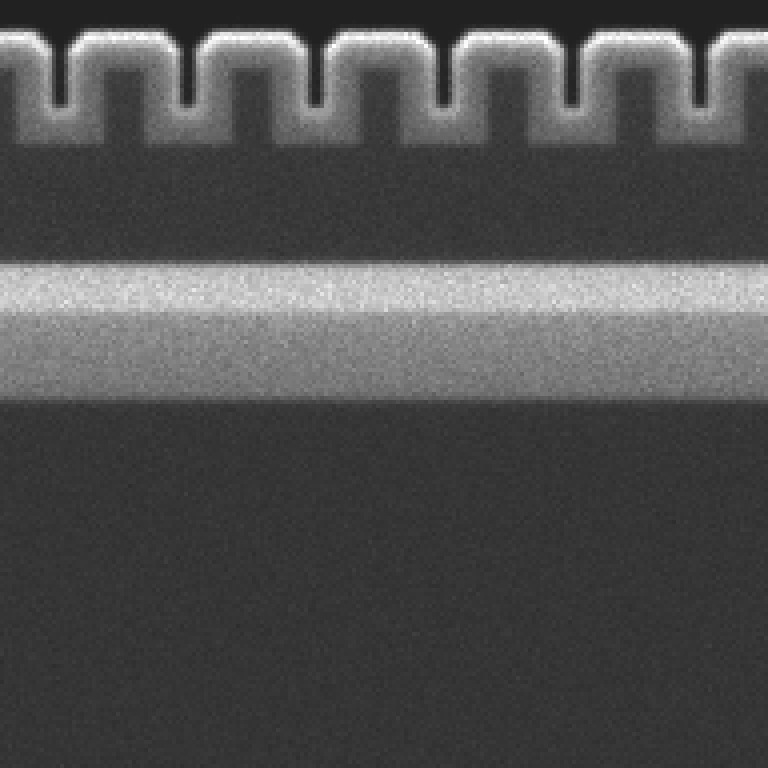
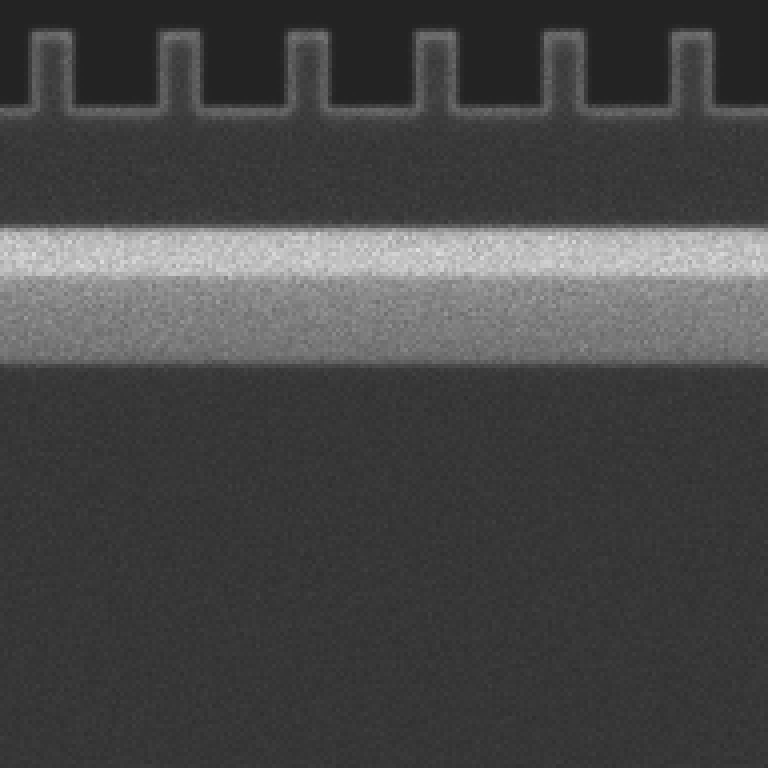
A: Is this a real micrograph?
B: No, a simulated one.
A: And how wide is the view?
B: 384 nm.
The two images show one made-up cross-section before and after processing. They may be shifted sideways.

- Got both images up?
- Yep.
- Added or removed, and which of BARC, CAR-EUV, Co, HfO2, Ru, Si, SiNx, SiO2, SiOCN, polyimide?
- removed, SiO2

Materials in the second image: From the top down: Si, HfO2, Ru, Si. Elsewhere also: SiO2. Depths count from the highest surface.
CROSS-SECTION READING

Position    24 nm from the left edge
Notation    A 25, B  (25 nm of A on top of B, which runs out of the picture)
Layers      Si 98, HfO2 24, Ru 44, Si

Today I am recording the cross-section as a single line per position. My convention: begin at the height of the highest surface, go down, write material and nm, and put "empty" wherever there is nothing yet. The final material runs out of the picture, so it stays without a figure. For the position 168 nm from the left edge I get empty 38, Si 60, HfO2 24, Ru 44, Si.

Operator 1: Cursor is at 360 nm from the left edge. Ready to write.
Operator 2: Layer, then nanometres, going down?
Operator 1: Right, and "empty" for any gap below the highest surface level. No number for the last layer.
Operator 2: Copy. empty 38, Si 60, HfO2 24, Ru 44, Si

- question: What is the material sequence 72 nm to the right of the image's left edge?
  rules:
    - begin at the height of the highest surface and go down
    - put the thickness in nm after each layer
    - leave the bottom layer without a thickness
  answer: empty 38, Si 60, HfO2 24, Ru 44, Si